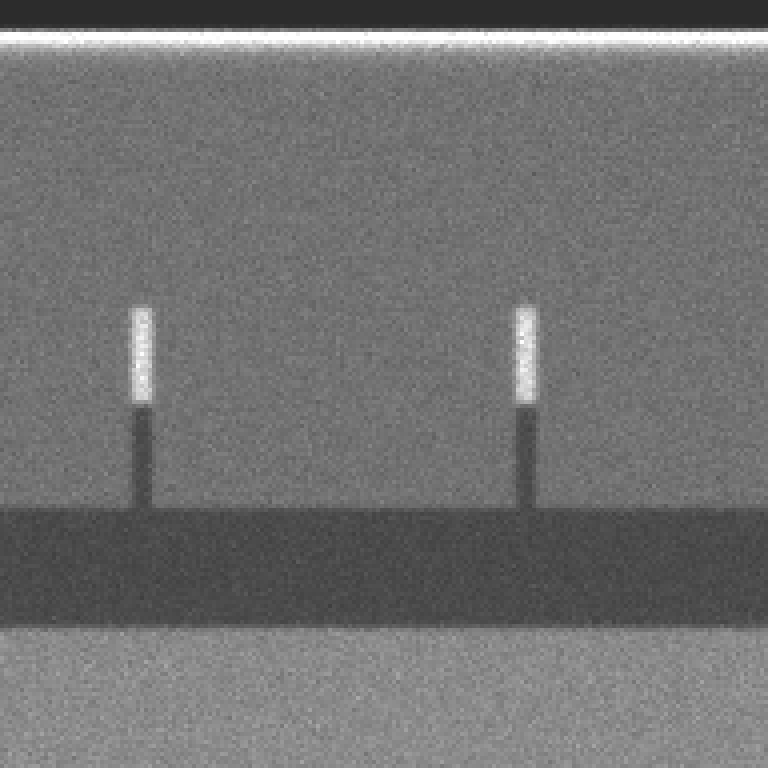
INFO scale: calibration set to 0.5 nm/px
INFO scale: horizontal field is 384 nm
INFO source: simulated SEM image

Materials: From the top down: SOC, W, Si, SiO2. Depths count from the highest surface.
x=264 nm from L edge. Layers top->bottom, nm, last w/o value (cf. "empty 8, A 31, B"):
SOC 138, W 48, Si 112, SiO2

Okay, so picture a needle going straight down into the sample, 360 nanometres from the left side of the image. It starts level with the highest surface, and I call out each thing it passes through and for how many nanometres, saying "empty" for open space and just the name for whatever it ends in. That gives SOC 238, Si 60, SiO2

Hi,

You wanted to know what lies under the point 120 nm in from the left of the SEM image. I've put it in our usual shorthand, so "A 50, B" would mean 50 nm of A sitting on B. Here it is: SOC 238, Si 60, SiO2